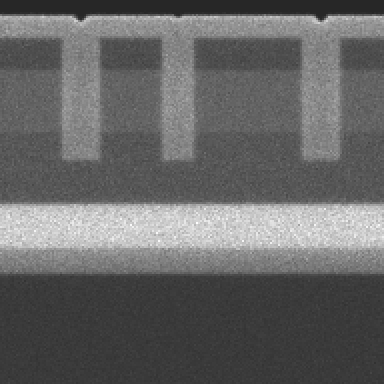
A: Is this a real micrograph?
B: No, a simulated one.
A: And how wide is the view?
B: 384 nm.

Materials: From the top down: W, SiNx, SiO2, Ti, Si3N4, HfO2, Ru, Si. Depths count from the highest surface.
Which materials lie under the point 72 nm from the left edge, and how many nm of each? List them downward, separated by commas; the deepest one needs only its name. W 144, Ti 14, Si3N4 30, HfO2 44, Ru 26, Si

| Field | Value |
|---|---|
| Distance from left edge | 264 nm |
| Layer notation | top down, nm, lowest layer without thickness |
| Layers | W 22, SiNx 32, SiO2 62, Ti 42, Si3N4 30, HfO2 44, Ru 26, Si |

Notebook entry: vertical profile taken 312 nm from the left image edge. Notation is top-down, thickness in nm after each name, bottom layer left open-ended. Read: W 144, Ti 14, Si3N4 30, HfO2 44, Ru 26, Si